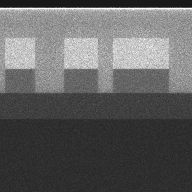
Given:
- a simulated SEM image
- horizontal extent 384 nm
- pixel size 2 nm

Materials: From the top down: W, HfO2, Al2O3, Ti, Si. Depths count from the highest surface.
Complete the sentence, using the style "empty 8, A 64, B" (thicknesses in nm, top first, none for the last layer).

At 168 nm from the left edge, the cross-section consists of W 60, HfO2 62, Al2O3 48, Ti 52, Si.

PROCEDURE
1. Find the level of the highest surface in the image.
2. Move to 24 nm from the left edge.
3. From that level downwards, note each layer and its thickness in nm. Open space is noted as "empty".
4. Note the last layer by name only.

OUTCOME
W 60, HfO2 62, Al2O3 48, Ti 52, Si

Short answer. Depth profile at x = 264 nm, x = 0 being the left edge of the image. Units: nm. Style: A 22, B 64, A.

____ W 60, HfO2 62, Al2O3 48, Ti 52, Si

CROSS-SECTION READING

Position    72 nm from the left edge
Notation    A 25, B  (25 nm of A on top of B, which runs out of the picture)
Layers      W 170, Ti 52, Si